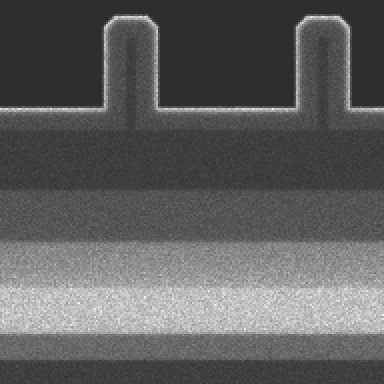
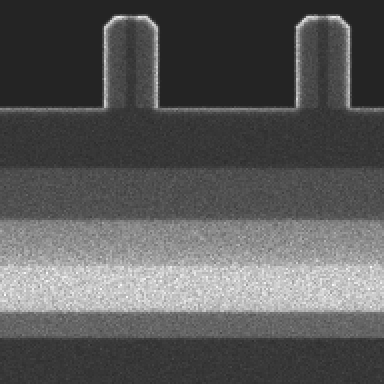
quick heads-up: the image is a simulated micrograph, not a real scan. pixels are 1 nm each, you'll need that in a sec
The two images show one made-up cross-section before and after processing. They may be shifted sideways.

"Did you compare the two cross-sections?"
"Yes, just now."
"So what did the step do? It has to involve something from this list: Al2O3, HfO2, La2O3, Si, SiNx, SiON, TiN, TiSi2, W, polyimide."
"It removed SiNx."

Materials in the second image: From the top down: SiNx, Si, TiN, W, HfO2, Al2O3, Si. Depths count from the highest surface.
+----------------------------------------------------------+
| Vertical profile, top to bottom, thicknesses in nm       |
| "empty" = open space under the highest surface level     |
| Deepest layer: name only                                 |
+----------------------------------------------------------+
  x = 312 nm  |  SiNx 92, Si 60, TiN 52, W 46, HfO2 46, Al2O3 26, Si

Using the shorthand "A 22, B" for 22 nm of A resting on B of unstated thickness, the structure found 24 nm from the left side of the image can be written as empty 92, Si 60, TiN 52, W 46, HfO2 46, Al2O3 26, Si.